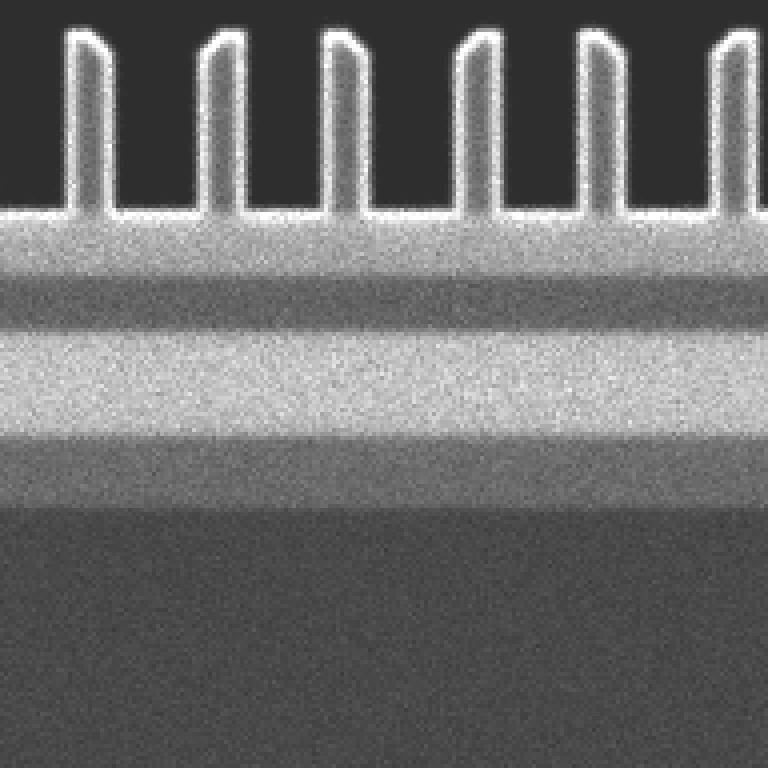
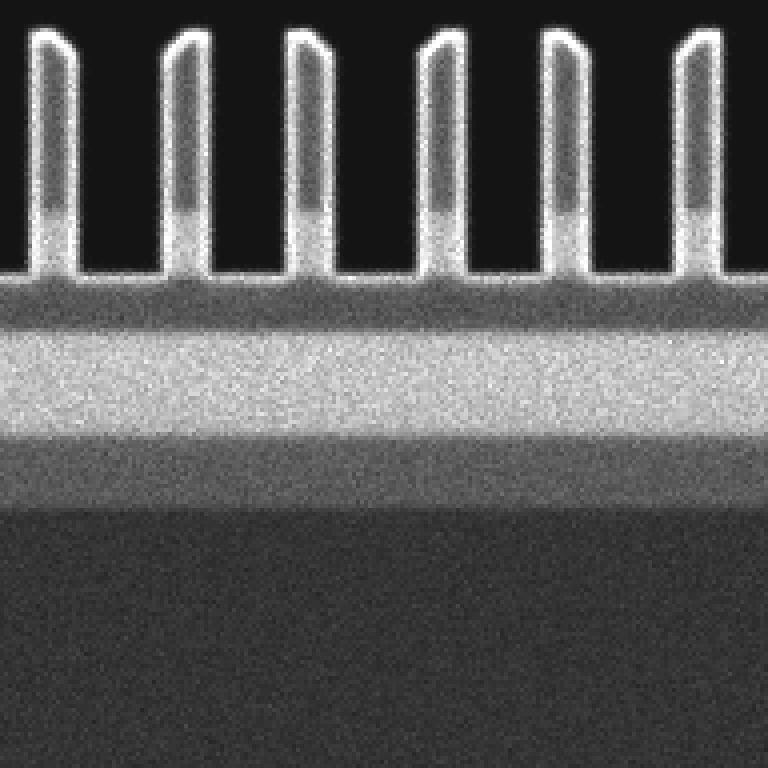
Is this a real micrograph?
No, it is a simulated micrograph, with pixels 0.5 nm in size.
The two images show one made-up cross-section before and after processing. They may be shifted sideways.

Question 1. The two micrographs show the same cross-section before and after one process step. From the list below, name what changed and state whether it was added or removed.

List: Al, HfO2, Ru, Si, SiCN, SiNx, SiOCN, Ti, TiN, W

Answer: Ru, removed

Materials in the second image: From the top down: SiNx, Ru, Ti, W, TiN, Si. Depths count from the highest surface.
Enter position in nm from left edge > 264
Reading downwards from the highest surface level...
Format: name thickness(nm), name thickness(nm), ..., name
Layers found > empty 122, Ti 28, W 52, TiN 36, Si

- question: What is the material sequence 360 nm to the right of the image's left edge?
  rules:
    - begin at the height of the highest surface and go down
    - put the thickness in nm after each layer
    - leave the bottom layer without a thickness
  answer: empty 122, Ti 28, W 52, TiN 36, Si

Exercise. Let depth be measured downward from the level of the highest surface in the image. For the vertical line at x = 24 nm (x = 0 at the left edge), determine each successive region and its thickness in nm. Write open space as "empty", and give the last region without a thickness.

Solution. SiNx 90, Ru 32, Ti 28, W 52, TiN 36, Si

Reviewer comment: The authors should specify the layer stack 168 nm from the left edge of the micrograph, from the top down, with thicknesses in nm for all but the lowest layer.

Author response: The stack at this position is empty 122, Ti 28, W 52, TiN 36, Si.